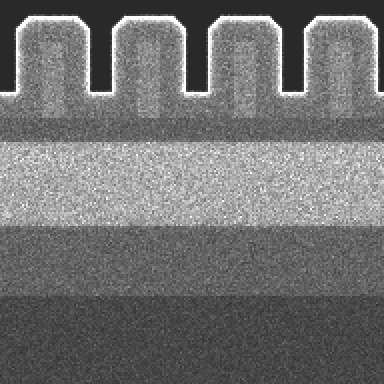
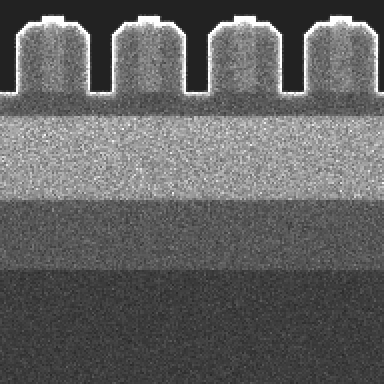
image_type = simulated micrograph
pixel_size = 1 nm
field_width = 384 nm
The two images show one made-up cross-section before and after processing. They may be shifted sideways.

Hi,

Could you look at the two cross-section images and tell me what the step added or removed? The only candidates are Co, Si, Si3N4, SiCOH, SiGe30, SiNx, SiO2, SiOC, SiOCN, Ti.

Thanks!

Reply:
removed Si3N4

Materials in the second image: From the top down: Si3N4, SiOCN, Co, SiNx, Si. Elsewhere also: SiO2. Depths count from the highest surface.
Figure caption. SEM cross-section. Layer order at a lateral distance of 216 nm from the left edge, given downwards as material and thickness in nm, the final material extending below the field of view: empty 10, Si3N4 66, SiOCN 24, Co 84, SiNx 70, Si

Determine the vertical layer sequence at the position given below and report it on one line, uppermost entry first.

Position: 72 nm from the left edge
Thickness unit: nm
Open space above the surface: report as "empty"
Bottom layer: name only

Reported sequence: empty 6, Si3N4 70, SiOCN 24, Co 84, SiNx 70, Si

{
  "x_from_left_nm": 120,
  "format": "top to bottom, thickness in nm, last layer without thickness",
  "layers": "empty 10, Si3N4 66, SiOCN 24, Co 84, SiNx 70, Si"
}